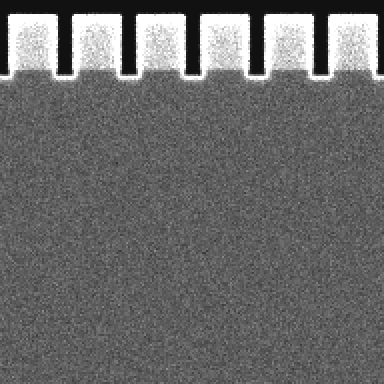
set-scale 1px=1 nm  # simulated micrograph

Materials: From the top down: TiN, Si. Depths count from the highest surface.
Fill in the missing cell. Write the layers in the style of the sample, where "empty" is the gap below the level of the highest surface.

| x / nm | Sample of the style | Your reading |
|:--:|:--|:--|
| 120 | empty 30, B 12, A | empty 60, Si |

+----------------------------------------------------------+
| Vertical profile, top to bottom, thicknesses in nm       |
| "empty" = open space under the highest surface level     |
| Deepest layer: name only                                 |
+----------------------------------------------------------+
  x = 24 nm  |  TiN 54, Si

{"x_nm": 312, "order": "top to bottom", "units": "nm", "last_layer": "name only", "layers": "empty 60, Si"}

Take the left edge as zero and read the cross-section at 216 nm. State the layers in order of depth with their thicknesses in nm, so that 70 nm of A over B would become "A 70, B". TiN 54, Si